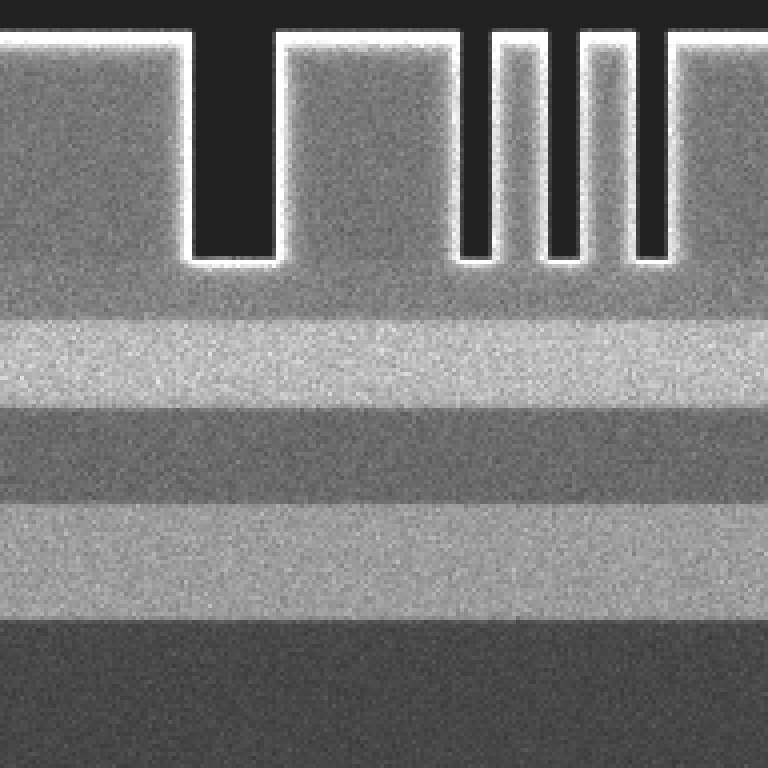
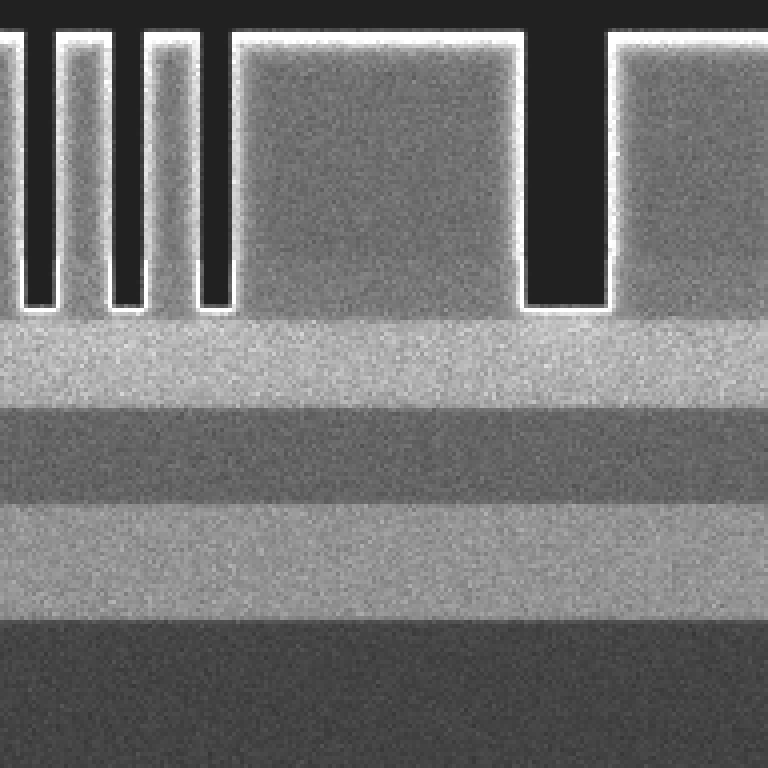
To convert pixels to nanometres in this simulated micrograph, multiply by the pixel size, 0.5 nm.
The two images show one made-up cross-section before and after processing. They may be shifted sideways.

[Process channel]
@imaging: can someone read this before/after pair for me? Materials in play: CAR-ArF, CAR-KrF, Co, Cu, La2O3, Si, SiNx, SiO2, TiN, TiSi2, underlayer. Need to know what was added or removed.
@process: TiN removed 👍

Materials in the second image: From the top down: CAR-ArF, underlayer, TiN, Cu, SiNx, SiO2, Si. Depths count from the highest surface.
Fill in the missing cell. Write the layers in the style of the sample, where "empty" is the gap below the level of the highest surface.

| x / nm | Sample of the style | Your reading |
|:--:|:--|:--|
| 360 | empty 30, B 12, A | CAR-ArF 60, underlayer 54, TiN 30, Cu 44, SiNx 48, SiO2 58, Si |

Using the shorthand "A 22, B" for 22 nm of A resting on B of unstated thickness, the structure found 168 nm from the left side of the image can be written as CAR-ArF 60, underlayer 54, TiN 30, Cu 44, SiNx 48, SiO2 58, Si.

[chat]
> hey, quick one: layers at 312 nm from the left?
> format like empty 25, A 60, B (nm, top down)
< CAR-ArF 60, underlayer 54, TiN 30, Cu 44, SiNx 48, SiO2 58, Si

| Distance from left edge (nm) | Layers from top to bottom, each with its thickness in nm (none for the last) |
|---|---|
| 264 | empty 138, TiN 6, Cu 44, SiNx 48, SiO2 58, Si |